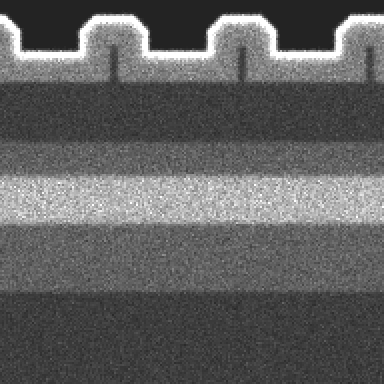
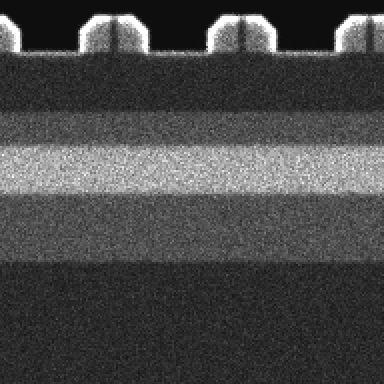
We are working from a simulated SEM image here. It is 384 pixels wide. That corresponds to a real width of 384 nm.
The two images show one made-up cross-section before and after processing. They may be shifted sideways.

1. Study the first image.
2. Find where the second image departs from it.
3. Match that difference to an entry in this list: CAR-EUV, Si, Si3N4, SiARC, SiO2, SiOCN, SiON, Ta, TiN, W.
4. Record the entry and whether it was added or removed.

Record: SiO2 / removed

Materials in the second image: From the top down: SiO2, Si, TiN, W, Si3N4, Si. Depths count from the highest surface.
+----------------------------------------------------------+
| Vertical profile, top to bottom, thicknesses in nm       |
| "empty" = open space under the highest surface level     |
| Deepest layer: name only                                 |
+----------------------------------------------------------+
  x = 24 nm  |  empty 36, Si 60, TiN 34, W 48, Si3N4 68, Si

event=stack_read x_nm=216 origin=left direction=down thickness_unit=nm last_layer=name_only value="empty 6, SiO2 30, Si 60, TiN 34, W 48, Si3N4 68, Si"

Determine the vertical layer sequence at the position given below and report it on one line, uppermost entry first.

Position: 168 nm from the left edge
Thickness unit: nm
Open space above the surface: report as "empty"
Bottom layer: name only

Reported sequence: empty 36, Si 60, TiN 34, W 48, Si3N4 68, Si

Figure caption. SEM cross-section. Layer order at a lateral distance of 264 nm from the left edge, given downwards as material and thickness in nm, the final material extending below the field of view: empty 4, SiO2 32, Si 60, TiN 34, W 48, Si3N4 68, Si